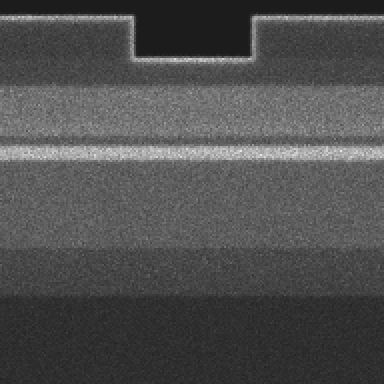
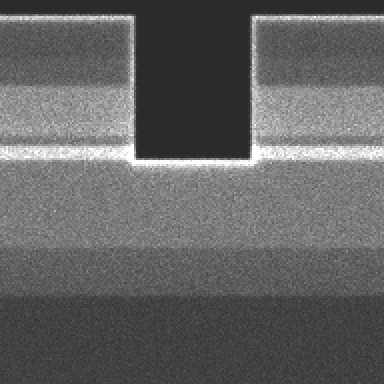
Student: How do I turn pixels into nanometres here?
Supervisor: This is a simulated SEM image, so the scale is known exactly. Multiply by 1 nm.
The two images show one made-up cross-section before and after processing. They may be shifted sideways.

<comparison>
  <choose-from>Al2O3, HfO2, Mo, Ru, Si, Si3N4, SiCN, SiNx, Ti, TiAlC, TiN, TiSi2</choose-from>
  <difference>HfO2 and Ru and Si3N4 and TiN removed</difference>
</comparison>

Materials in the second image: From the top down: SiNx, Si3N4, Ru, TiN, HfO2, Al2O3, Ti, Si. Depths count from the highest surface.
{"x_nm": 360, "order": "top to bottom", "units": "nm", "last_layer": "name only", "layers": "SiNx 42, Si3N4 28, Ru 50, TiN 10, HfO2 14, Al2O3 88, Ti 48, Si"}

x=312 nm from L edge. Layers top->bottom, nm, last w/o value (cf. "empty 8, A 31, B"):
SiNx 42, Si3N4 28, Ru 50, TiN 10, HfO2 14, Al2O3 88, Ti 48, Si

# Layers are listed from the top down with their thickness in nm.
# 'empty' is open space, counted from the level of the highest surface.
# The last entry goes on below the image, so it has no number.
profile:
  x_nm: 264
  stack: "SiNx 42, Si3N4 28, Ru 50, TiN 10, HfO2 14, Al2O3 88, Ti 48, Si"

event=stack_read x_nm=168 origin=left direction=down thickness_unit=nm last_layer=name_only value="empty 144, Al2O3 88, Ti 48, Si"